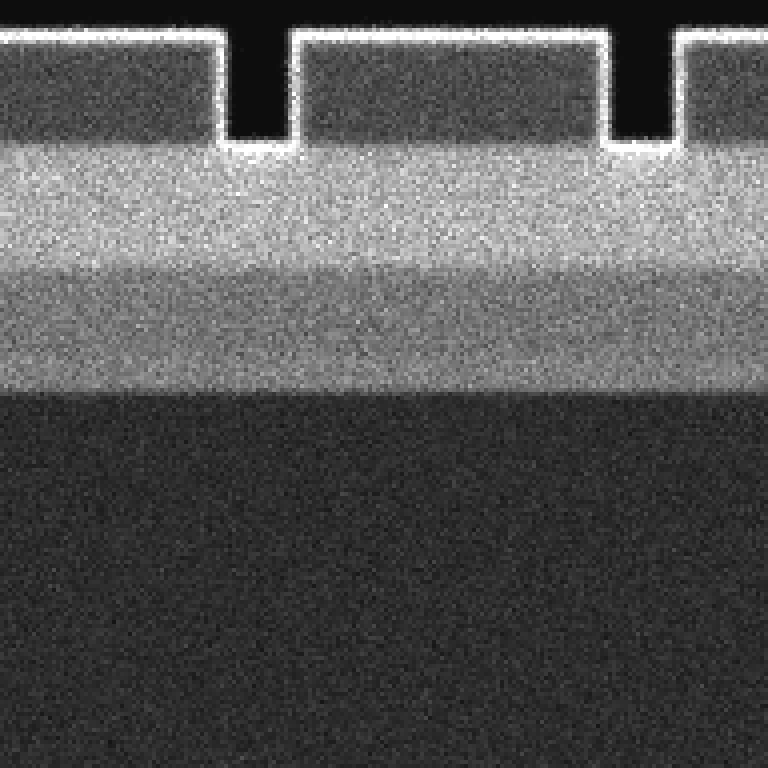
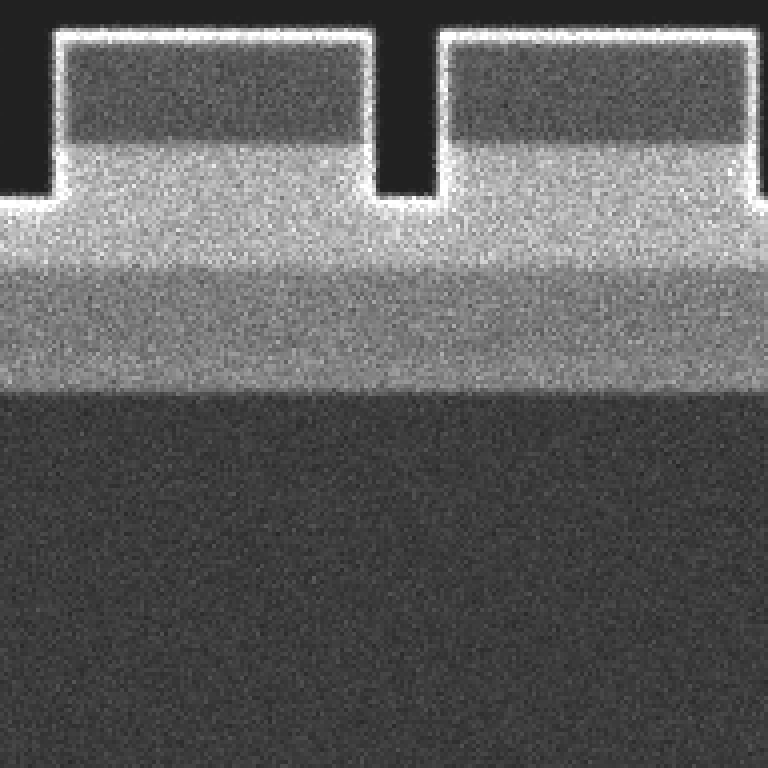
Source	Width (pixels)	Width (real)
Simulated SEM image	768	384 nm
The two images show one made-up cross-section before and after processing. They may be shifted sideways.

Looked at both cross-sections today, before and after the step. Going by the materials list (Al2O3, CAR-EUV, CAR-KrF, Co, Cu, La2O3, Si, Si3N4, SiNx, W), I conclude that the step removed W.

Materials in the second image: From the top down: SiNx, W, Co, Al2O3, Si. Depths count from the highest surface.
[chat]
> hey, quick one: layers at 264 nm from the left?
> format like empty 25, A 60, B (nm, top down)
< SiNx 56, W 62, Co 44, Al2O3 18, Si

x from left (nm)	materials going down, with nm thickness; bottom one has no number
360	SiNx 56, W 62, Co 44, Al2O3 18, Si